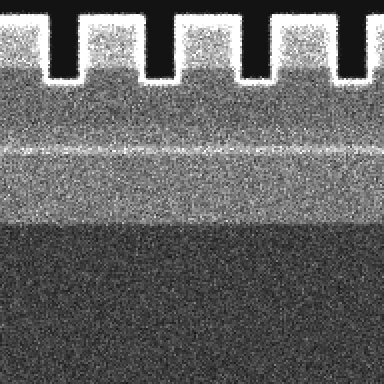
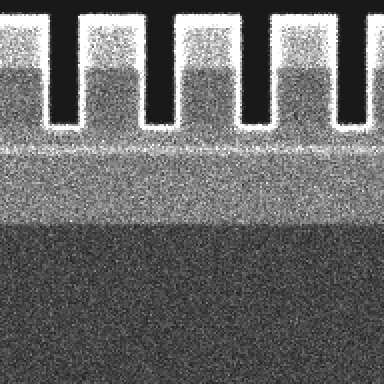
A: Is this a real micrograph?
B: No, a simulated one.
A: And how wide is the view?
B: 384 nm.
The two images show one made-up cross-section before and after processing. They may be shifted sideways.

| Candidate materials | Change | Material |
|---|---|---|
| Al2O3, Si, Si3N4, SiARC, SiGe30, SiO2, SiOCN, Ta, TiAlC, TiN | removed | SiOCN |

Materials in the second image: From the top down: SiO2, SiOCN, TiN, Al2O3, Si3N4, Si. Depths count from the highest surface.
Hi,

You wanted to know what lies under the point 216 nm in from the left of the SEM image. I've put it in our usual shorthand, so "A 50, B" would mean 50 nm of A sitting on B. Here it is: SiO2 52, SiOCN 58, TiN 20, Al2O3 8, Si3N4 70, Si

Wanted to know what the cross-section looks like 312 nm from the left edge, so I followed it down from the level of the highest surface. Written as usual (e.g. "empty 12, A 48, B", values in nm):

SiO2 52, SiOCN 58, TiN 20, Al2O3 8, Si3N4 70, Si